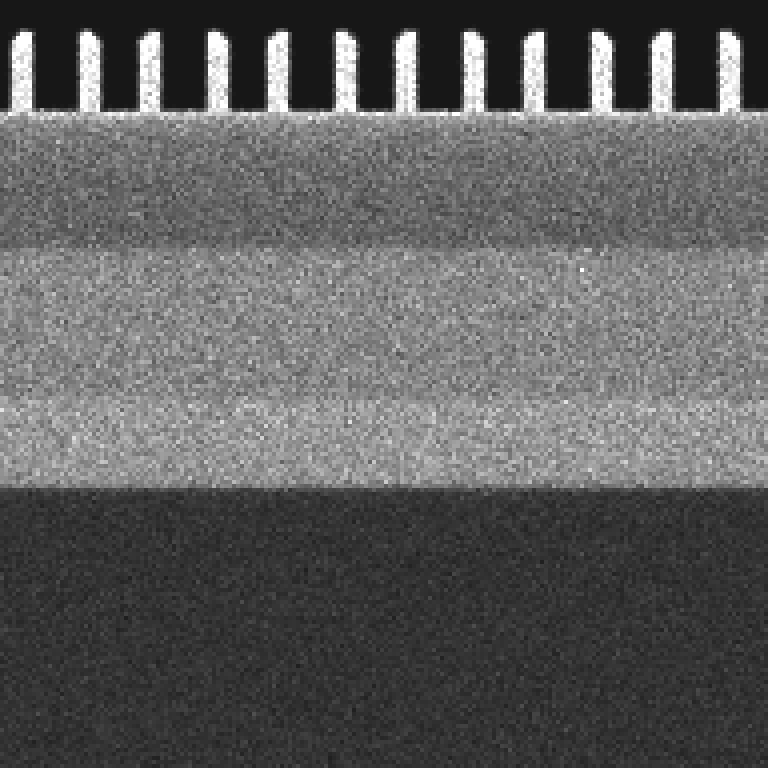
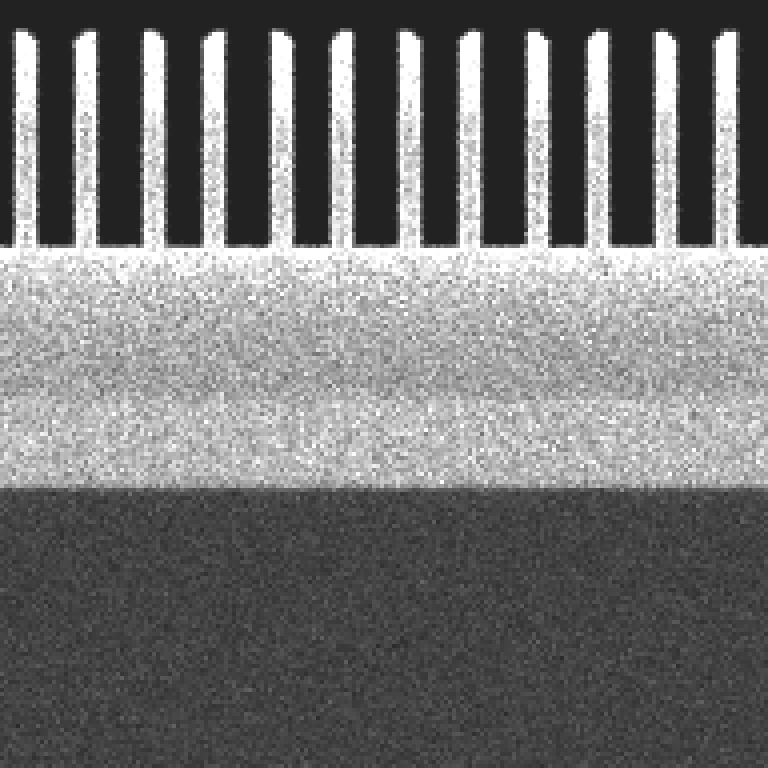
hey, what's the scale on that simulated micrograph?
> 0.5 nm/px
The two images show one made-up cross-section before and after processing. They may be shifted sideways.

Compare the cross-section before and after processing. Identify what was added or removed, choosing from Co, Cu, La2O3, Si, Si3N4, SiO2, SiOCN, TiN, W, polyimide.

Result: TiN removed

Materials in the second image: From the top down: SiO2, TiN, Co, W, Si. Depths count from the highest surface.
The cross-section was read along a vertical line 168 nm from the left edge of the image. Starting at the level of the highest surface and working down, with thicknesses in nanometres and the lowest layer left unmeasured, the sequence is empty 2, SiO2 38, TiN 68, Co 76, W 44, Si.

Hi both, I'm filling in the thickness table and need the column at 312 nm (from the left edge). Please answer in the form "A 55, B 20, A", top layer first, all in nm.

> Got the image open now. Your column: empty 108, Co 76, W 44, Si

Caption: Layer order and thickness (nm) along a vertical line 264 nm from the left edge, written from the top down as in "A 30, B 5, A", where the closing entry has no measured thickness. SiO2 40, TiN 68, Co 76, W 44, Si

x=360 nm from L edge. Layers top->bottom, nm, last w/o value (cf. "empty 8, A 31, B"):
empty 2, SiO2 38, TiN 68, Co 76, W 44, Si